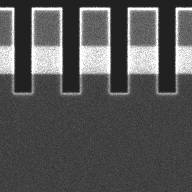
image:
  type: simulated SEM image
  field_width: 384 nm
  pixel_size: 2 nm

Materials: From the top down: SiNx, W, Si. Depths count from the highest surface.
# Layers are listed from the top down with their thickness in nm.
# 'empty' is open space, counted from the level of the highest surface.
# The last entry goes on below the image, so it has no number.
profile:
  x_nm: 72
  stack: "SiNx 76, W 56, Si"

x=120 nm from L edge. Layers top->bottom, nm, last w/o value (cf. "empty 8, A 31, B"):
SiNx 76, W 56, Si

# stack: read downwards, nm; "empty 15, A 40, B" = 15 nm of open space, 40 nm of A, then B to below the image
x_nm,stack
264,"SiNx 76, W 56, Si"